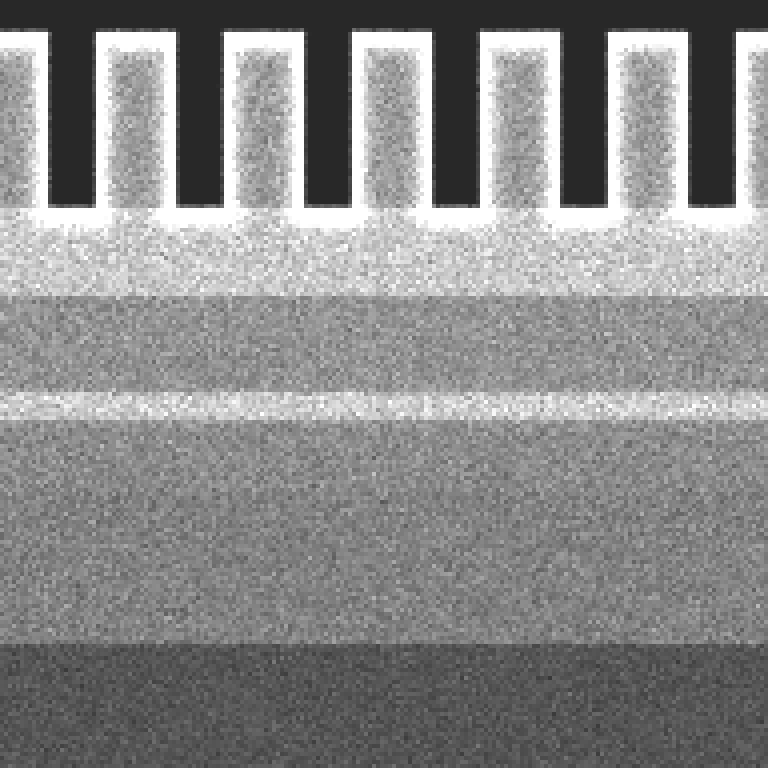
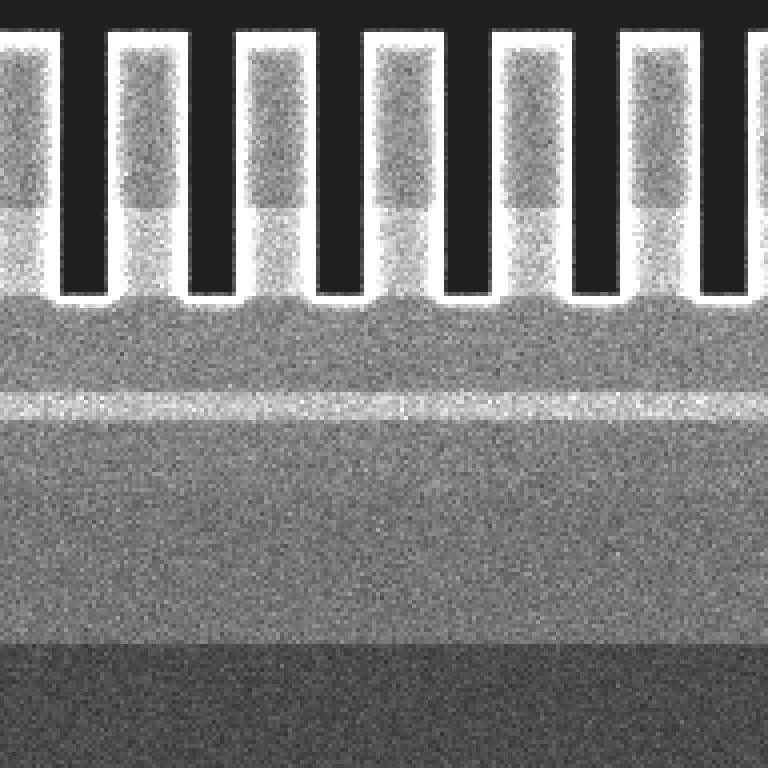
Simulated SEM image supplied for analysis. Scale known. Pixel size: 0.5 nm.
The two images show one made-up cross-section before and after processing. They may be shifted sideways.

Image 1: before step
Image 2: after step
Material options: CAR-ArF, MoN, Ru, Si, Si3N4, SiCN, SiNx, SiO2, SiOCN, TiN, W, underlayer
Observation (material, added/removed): SiO2, removed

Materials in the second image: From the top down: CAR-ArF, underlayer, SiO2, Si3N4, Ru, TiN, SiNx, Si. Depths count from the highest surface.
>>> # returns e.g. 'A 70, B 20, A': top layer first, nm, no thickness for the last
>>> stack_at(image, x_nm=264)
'CAR-ArF 46, underlayer 42, SiO2 44, Si3N4 48, Ru 14, TiN 36, SiNx 76, Si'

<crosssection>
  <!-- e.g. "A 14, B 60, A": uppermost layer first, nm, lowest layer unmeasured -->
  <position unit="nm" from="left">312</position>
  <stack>CAR-ArF 46, underlayer 42, SiO2 44, Si3N4 48, Ru 14, TiN 36, SiNx 76, Si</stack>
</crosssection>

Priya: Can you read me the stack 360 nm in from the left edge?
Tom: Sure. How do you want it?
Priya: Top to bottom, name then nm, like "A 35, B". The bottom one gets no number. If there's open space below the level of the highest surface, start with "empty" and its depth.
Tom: empty 132, Si3N4 48, Ru 14, TiN 36, SiNx 76, Si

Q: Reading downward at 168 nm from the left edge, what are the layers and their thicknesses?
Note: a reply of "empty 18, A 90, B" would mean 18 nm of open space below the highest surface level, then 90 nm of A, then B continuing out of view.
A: empty 132, Si3N4 48, Ru 14, TiN 36, SiNx 76, Si